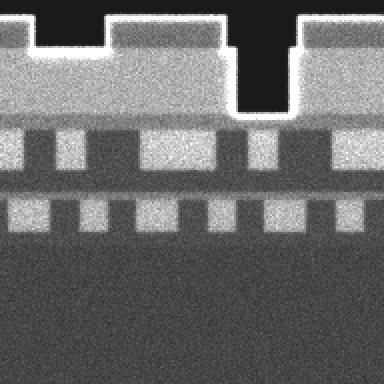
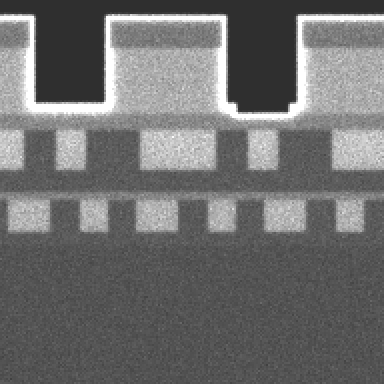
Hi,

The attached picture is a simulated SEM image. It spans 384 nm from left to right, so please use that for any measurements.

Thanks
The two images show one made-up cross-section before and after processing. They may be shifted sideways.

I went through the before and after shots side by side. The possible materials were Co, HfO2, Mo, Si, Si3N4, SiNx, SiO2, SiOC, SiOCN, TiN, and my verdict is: removed, SiO2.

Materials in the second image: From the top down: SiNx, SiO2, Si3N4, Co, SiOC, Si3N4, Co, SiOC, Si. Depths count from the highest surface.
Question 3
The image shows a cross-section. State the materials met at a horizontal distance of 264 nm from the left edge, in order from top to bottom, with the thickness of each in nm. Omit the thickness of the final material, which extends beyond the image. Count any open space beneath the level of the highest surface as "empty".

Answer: empty 98, Si3N4 16, Co 40, SiOC 22, Si3N4 8, Co 32, SiOC 14, Si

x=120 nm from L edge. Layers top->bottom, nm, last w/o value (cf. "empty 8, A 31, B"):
SiNx 32, SiO2 66, Si3N4 16, SiOC 62, Si3N4 8, SiOC 46, Si